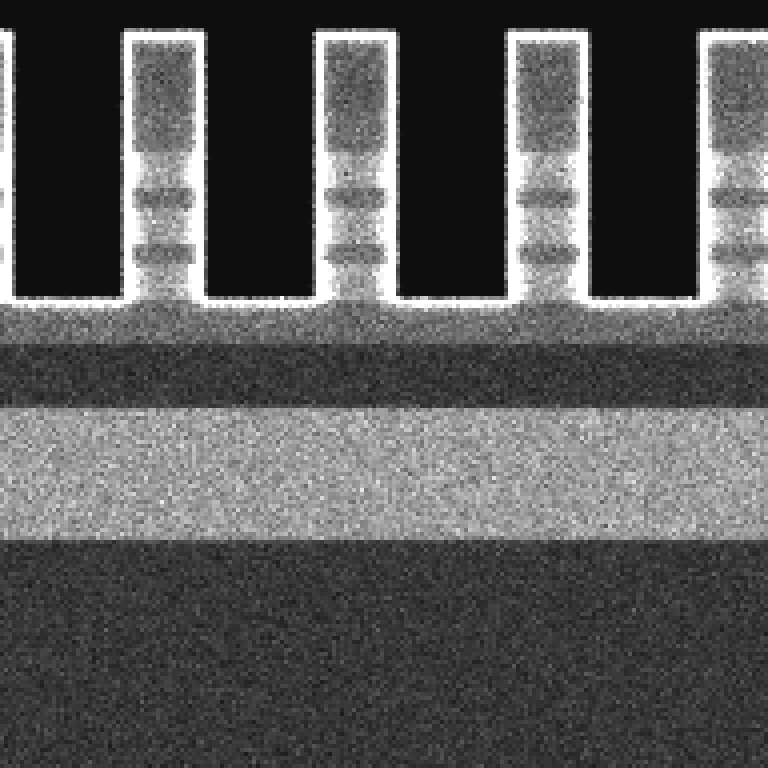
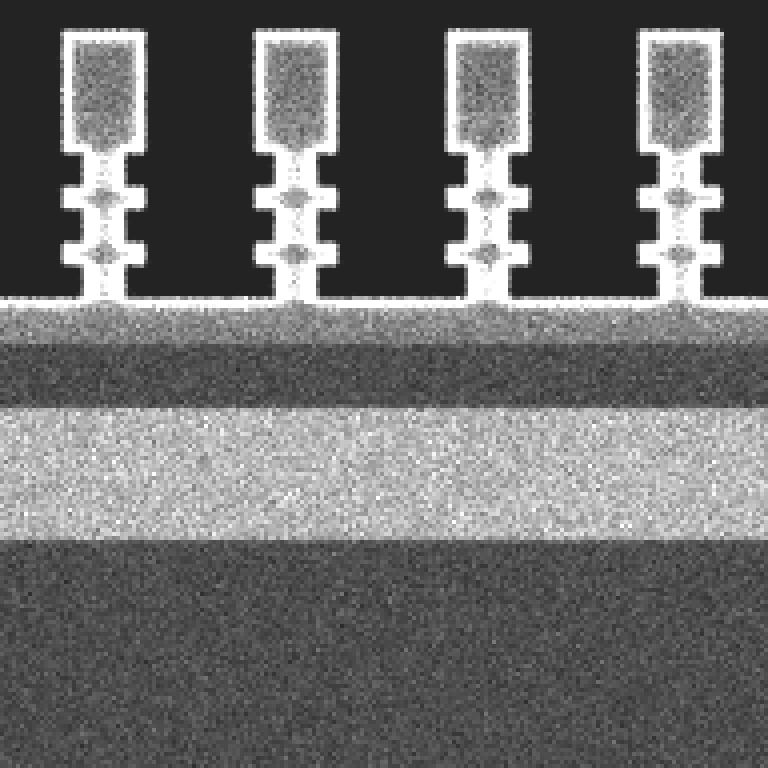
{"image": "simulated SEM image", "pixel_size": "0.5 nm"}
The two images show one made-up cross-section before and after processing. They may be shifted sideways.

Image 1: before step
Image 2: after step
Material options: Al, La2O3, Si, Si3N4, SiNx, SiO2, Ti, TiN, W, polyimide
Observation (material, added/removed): SiO2, removed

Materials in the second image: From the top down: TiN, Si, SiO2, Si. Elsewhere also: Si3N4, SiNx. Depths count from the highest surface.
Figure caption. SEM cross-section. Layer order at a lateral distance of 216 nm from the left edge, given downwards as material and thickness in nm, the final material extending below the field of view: empty 134, TiN 22, Si 32, SiO2 66, Si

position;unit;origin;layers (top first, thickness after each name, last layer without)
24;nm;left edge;empty 134, TiN 22, Si 32, SiO2 66, Si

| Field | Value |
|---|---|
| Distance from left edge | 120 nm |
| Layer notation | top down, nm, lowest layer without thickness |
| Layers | empty 134, TiN 22, Si 32, SiO2 66, Si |